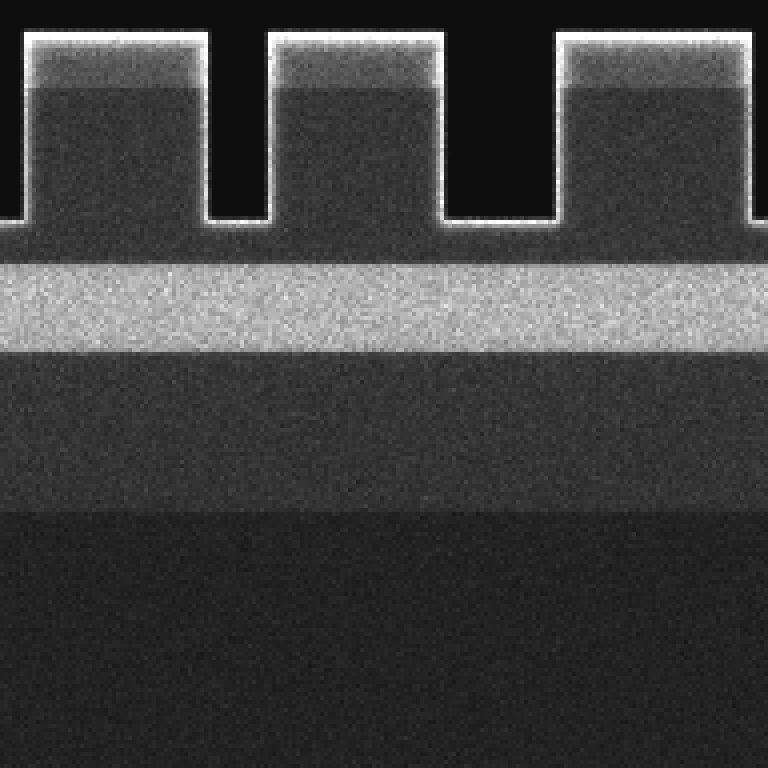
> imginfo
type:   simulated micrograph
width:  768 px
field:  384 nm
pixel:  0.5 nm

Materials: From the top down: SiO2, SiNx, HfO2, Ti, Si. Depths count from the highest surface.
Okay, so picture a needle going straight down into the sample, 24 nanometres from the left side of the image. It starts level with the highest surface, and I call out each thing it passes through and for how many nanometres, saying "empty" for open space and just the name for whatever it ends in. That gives SiO2 28, SiNx 88, HfO2 44, Ti 80, Si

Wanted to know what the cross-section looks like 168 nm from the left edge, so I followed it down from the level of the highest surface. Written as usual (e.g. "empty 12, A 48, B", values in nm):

SiO2 28, SiNx 88, HfO2 44, Ti 80, Si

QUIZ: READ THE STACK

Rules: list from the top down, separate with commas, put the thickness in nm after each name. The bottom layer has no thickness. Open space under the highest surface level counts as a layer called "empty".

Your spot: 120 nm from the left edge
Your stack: empty 94, SiNx 22, HfO2 44, Ti 80, Si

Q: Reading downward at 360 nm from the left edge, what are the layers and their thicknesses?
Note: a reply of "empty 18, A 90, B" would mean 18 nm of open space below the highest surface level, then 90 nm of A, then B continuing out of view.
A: SiO2 28, SiNx 88, HfO2 44, Ti 80, Si